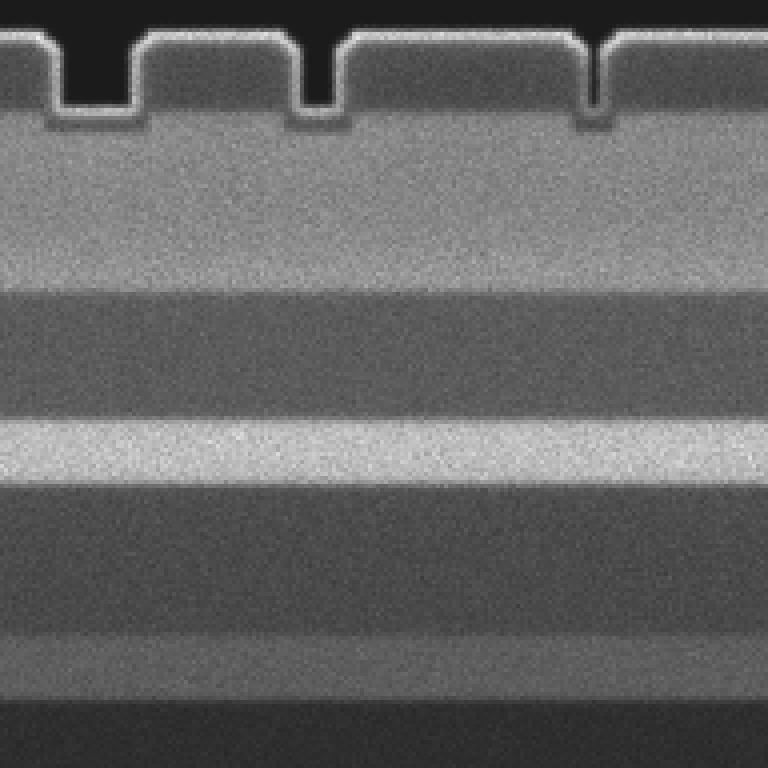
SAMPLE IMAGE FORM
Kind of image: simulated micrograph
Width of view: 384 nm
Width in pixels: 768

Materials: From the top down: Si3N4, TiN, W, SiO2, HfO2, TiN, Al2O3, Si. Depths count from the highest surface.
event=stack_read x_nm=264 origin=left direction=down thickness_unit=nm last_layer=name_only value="Si3N4 12, TiN 28, W 90, SiO2 64, HfO2 32, TiN 76, Al2O3 32, Si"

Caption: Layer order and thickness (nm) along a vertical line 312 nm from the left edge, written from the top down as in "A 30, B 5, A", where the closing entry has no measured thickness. Si3N4 12, TiN 28, W 90, SiO2 64, HfO2 32, TiN 76, Al2O3 32, Si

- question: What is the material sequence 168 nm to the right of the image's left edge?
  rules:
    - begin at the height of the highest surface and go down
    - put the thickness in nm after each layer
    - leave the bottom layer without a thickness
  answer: empty 8, Si3N4 42, W 80, SiO2 64, HfO2 32, TiN 76, Al2O3 32, Si